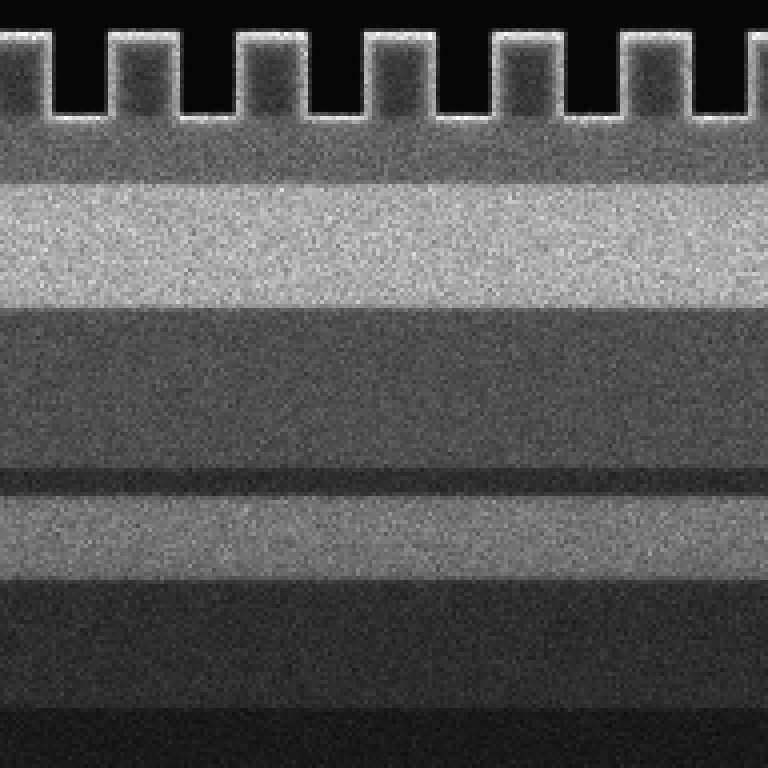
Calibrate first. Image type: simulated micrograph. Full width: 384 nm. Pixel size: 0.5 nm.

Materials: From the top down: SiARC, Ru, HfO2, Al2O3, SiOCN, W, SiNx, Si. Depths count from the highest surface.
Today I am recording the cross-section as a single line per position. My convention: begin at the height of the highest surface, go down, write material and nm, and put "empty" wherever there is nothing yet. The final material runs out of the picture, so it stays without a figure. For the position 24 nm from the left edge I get SiARC 42, Ru 34, HfO2 62, Al2O3 80, SiOCN 14, W 42, SiNx 64, Si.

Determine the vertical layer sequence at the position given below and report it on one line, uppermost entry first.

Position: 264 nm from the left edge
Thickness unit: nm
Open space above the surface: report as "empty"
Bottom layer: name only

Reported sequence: SiARC 42, Ru 34, HfO2 62, Al2O3 80, SiOCN 14, W 42, SiNx 64, Si